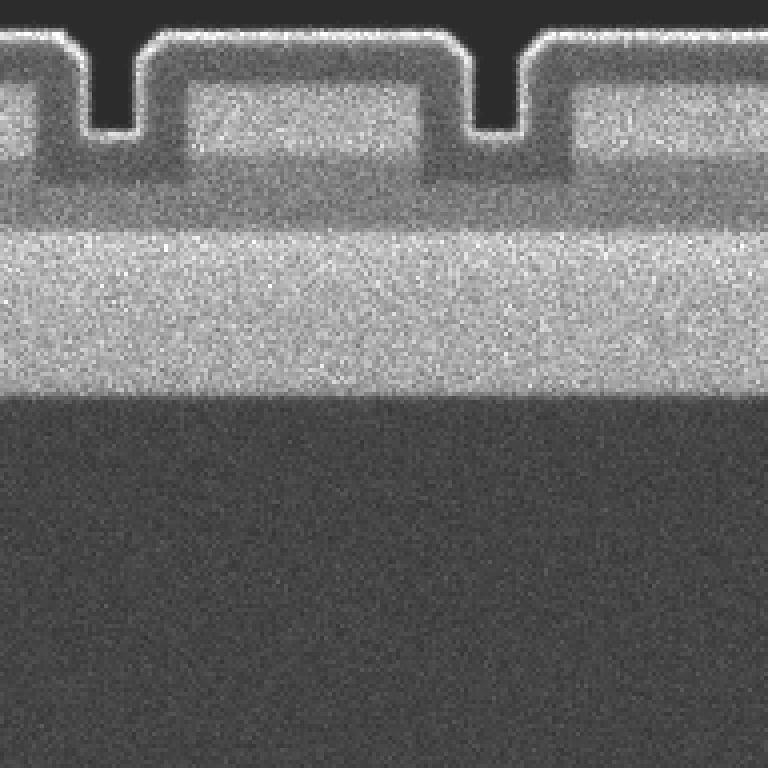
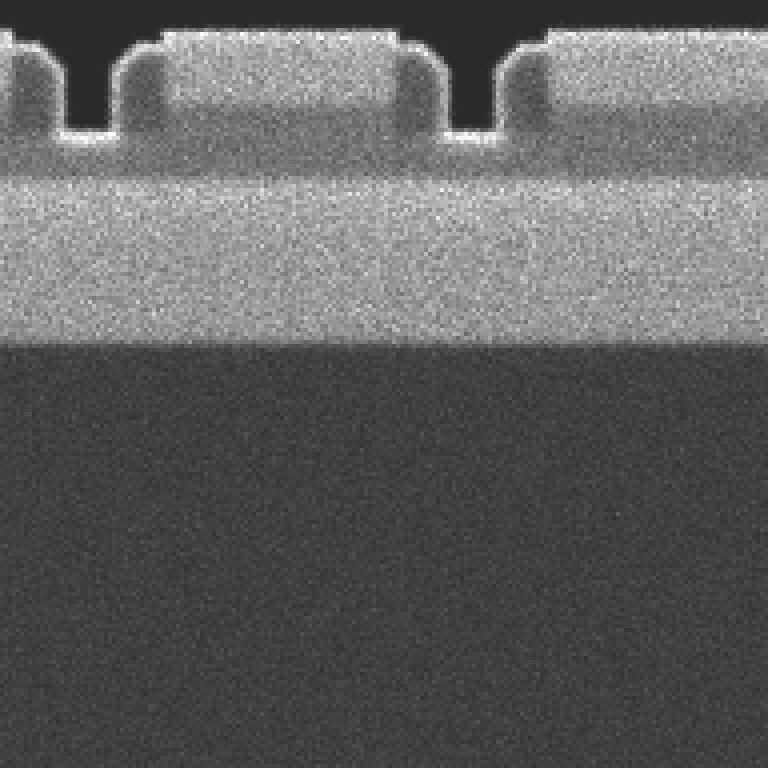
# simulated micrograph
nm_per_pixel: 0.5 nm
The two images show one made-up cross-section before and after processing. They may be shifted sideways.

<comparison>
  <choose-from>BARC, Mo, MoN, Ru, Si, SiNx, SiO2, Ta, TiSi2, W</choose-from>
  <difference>SiNx removed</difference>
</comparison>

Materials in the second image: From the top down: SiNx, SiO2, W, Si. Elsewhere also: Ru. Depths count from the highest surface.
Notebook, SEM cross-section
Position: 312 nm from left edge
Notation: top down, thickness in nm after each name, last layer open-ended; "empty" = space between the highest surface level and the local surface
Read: Ru 36, SiO2 38, W 82, Si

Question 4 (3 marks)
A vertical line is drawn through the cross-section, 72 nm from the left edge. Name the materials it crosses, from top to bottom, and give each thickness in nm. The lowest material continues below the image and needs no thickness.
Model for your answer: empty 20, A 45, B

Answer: empty 6, SiNx 44, SiO2 24, W 82, Si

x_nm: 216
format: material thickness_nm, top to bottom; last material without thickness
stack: empty 12, SiNx 38, SiO2 24, W 82, Si